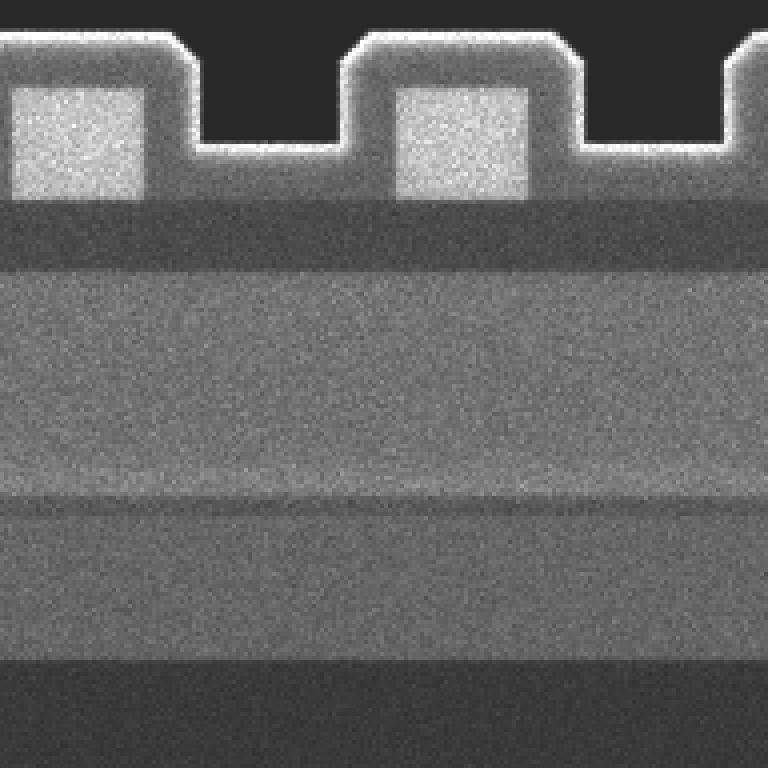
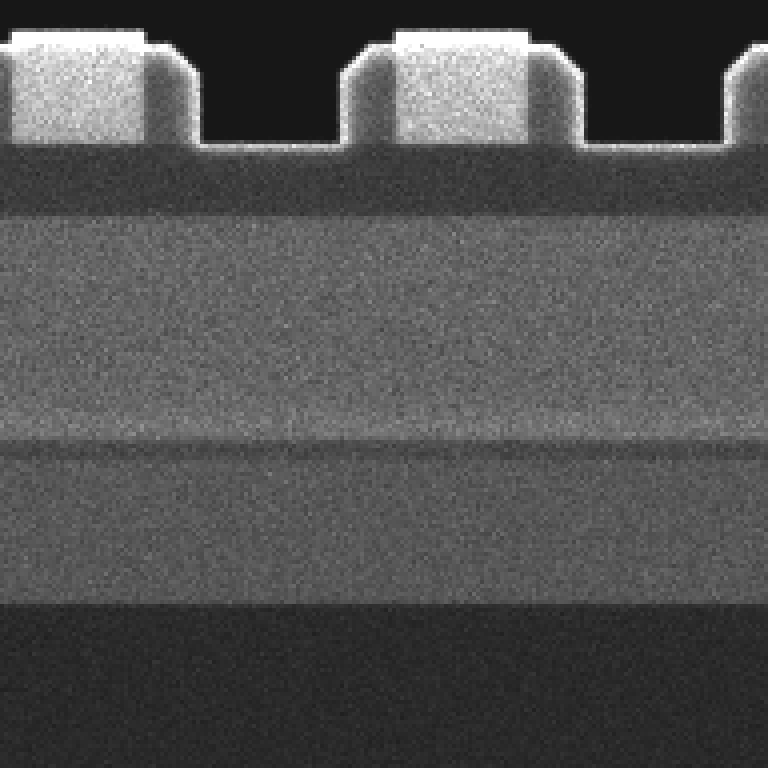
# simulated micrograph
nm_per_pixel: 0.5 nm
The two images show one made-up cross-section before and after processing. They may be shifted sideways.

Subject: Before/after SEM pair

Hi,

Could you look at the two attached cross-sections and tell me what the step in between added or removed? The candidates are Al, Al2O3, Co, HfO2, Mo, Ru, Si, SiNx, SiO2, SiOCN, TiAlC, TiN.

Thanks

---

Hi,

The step removed SiO2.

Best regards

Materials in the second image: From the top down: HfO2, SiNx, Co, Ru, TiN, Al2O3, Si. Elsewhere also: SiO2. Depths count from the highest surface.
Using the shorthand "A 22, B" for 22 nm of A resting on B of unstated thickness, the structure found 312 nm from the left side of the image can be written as empty 56, SiNx 36, Co 98, Ru 14, TiN 10, Al2O3 72, Si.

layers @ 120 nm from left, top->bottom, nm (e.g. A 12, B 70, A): empty 56, SiNx 36, Co 98, Ru 14, TiN 10, Al2O3 72, Si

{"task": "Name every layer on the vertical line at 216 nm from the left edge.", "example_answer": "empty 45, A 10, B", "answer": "HfO2 56, SiNx 36, Co 98, Ru 14, TiN 10, Al2O3 72, Si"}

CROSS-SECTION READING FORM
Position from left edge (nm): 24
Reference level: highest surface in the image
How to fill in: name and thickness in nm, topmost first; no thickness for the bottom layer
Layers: HfO2 56, SiNx 36, Co 98, Ru 14, TiN 10, Al2O3 72, Si